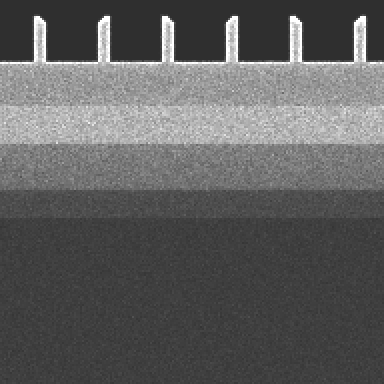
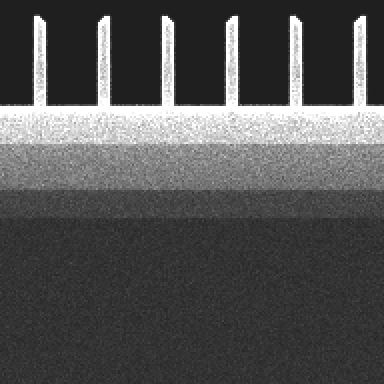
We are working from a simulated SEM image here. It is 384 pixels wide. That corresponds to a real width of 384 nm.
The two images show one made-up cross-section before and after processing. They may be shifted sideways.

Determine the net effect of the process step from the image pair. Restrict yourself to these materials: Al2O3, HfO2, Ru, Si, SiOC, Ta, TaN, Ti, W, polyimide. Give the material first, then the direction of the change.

W: removed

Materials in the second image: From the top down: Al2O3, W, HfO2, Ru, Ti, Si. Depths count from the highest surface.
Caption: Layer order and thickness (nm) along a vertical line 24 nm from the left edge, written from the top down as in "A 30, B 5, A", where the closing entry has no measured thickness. empty 90, HfO2 38, Ru 46, Ti 28, Si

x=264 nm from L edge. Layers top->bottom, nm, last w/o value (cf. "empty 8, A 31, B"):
empty 90, HfO2 38, Ru 46, Ti 28, Si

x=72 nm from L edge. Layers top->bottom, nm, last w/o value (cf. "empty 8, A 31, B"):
empty 90, HfO2 38, Ru 46, Ti 28, Si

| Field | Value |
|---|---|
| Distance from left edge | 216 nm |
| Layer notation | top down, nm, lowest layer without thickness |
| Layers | empty 90, HfO2 38, Ru 46, Ti 28, Si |